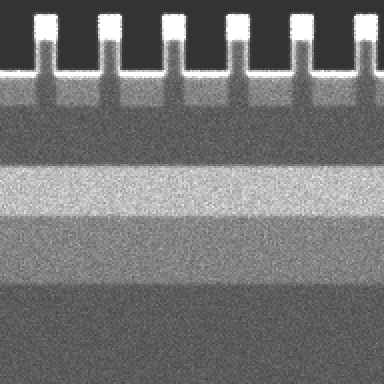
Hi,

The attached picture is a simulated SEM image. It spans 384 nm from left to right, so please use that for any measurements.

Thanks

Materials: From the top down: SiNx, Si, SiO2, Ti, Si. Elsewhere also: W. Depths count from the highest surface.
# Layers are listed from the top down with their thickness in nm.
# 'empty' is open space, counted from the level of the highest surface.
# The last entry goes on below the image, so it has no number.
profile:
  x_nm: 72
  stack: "empty 56, SiNx 34, Si 60, SiO2 50, Ti 68, Si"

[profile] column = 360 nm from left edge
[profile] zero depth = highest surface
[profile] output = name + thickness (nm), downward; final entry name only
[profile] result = W 24, Si 126, SiO2 50, Ti 68, Si